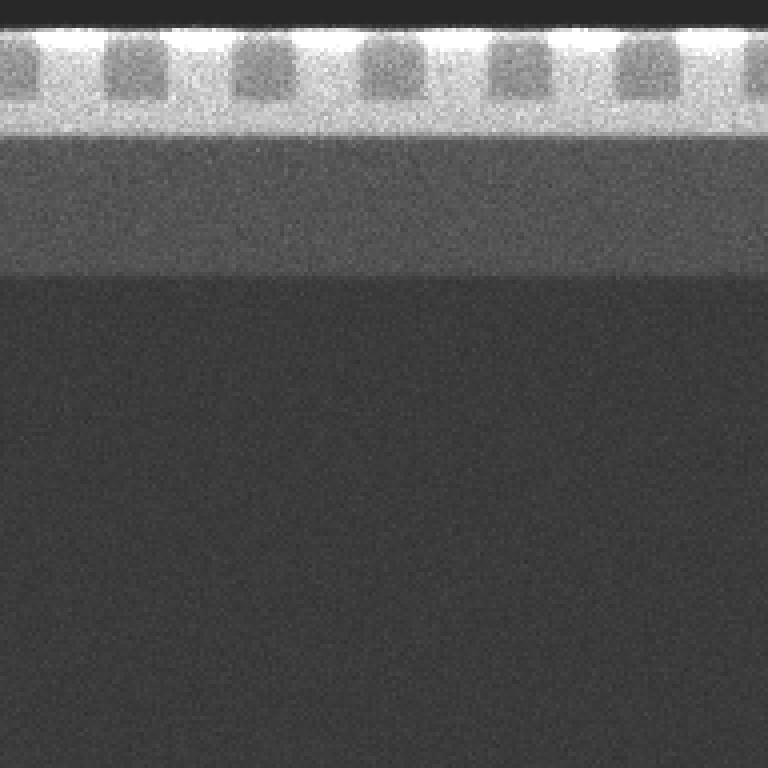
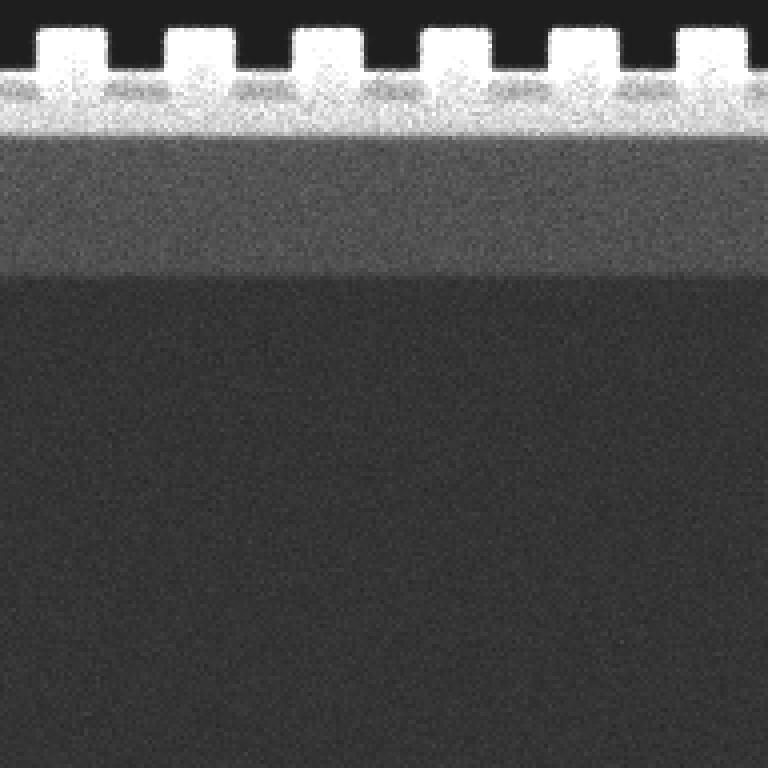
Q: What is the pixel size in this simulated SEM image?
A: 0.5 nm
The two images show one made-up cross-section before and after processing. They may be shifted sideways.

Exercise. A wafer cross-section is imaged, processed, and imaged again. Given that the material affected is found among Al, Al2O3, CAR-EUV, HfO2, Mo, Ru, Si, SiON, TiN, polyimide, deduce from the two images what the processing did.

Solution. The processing removed Ru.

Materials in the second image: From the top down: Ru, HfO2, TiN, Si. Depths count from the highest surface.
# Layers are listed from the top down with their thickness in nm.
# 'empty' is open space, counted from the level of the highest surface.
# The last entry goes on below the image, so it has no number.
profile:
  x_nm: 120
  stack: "empty 20, Ru 14, HfO2 18, TiN 70, Si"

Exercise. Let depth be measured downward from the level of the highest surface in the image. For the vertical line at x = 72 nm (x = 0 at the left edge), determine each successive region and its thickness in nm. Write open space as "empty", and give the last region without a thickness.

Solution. empty 20, Ru 14, HfO2 18, TiN 70, Si